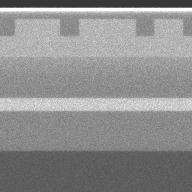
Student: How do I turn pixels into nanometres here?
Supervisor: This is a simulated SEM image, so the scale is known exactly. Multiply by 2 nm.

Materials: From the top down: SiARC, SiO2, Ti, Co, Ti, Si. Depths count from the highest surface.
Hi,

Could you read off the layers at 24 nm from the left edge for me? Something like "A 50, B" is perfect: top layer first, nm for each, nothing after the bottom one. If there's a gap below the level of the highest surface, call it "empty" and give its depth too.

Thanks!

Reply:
SiARC 56, SiO2 42, Ti 82, Co 26, Ti 80, Si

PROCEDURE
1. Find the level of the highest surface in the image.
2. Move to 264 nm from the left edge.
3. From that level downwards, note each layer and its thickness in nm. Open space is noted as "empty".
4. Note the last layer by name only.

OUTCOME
SiARC 22, SiO2 76, Ti 82, Co 26, Ti 80, Si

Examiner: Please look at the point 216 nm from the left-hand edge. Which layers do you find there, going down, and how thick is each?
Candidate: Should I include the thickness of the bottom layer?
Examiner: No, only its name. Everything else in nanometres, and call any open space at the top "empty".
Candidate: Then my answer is SiARC 22, SiO2 76, Ti 82, Co 26, Ti 80, Si